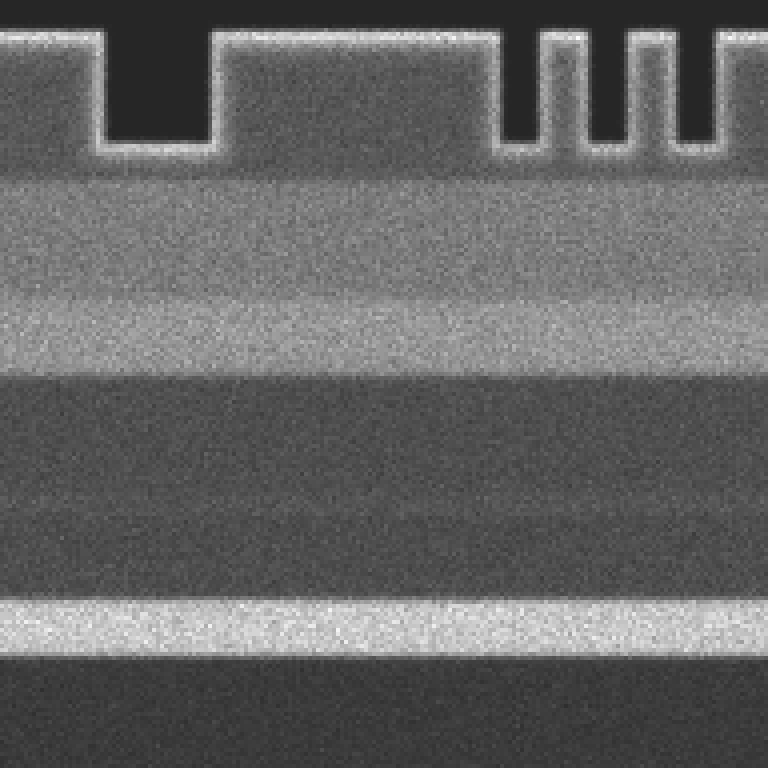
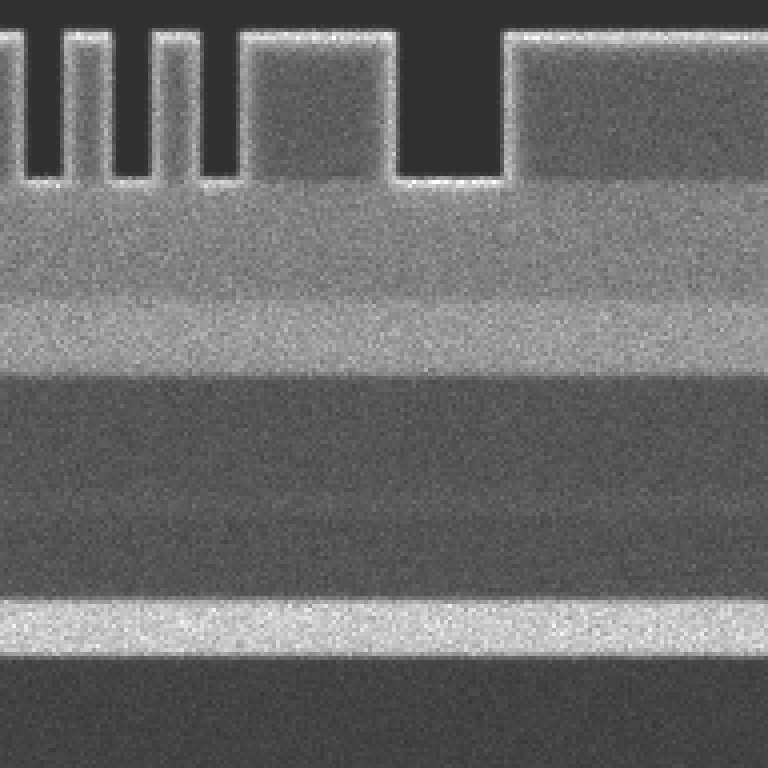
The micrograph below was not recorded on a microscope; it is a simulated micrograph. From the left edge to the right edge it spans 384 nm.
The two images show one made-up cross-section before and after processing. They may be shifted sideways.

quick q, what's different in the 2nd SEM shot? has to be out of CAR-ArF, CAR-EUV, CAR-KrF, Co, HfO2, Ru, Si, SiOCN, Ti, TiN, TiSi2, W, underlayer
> underlayer removed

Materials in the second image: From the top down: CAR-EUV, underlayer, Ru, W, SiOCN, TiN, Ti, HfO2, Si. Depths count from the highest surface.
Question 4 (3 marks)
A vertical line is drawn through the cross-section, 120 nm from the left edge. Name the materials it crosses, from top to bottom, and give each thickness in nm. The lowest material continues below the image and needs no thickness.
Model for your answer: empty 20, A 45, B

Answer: CAR-EUV 56, underlayer 18, Ru 60, W 38, SiOCN 58, TiN 12, Ti 42, HfO2 28, Si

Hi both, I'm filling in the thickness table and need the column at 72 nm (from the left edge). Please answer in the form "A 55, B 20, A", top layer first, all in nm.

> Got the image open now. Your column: empty 74, Ru 60, W 38, SiOCN 58, TiN 12, Ti 42, HfO2 28, Si